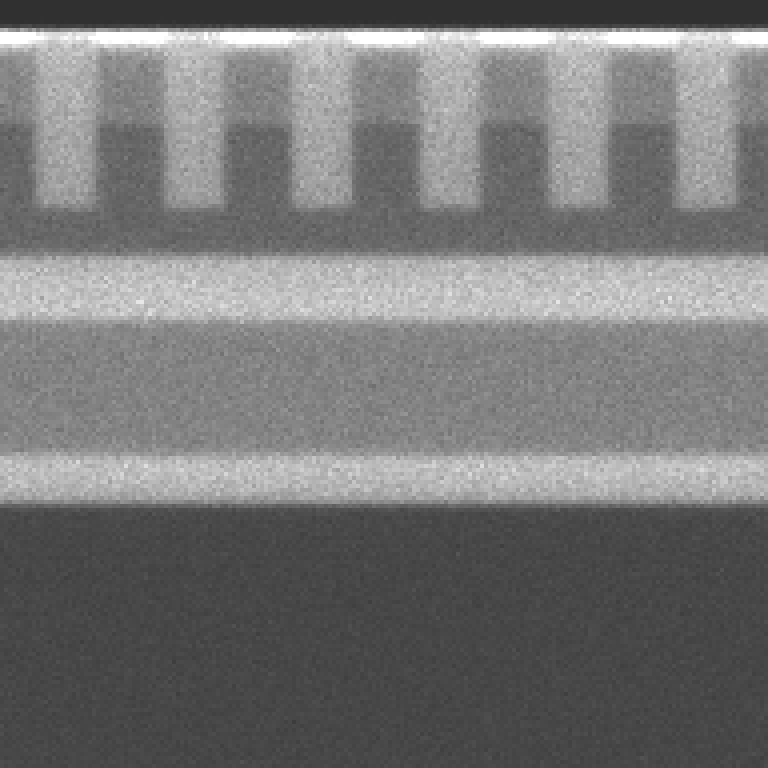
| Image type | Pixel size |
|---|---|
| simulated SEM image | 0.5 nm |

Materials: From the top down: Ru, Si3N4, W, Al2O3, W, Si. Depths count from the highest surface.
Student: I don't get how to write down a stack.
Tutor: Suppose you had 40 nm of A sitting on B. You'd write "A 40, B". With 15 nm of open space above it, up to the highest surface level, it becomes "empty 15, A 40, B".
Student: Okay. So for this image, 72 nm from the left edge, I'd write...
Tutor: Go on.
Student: Al2O3 46, Si3N4 66, W 32, Al2O3 68, W 24, Si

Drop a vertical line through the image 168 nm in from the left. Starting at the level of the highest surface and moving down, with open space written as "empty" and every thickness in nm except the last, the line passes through Ru 88, Si3N4 24, W 32, Al2O3 68, W 24, Si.